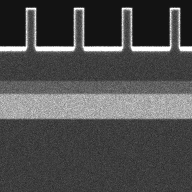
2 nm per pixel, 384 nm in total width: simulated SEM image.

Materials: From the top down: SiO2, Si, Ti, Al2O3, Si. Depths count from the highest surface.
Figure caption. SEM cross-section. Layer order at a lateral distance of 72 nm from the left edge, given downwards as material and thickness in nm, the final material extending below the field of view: empty 78, SiO2 8, Si 60, Ti 26, Al2O3 50, Si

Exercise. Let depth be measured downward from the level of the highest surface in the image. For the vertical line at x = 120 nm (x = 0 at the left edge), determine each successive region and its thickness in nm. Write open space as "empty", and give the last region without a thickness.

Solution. empty 78, SiO2 8, Si 60, Ti 26, Al2O3 50, Si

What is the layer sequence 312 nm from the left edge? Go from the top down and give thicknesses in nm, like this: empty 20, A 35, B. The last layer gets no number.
empty 78, SiO2 8, Si 60, Ti 26, Al2O3 50, Si